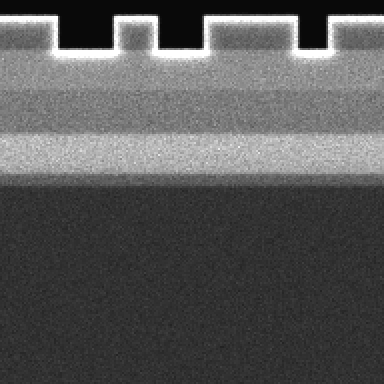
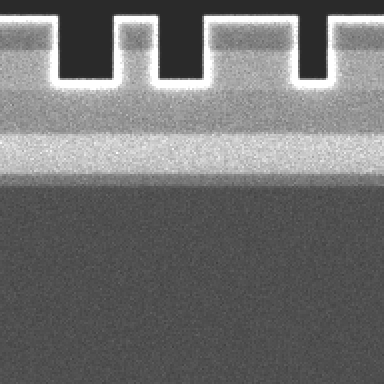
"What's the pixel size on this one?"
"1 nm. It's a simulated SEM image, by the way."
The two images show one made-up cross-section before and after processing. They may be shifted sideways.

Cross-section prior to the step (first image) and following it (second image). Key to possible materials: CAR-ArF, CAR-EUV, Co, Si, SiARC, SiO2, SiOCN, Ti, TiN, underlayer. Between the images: SiO2 was removed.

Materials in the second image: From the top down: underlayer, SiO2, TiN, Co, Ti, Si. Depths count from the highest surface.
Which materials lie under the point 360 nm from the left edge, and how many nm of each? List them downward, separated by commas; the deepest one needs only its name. underlayer 34, SiO2 40, TiN 44, Co 40, Ti 12, Si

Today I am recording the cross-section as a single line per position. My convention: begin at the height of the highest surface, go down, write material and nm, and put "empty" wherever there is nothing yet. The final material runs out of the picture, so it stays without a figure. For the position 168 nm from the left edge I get empty 64, SiO2 10, TiN 44, Co 40, Ti 12, Si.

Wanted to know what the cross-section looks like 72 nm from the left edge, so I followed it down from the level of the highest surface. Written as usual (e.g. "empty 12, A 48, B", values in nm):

empty 64, SiO2 10, TiN 44, Co 40, Ti 12, Si